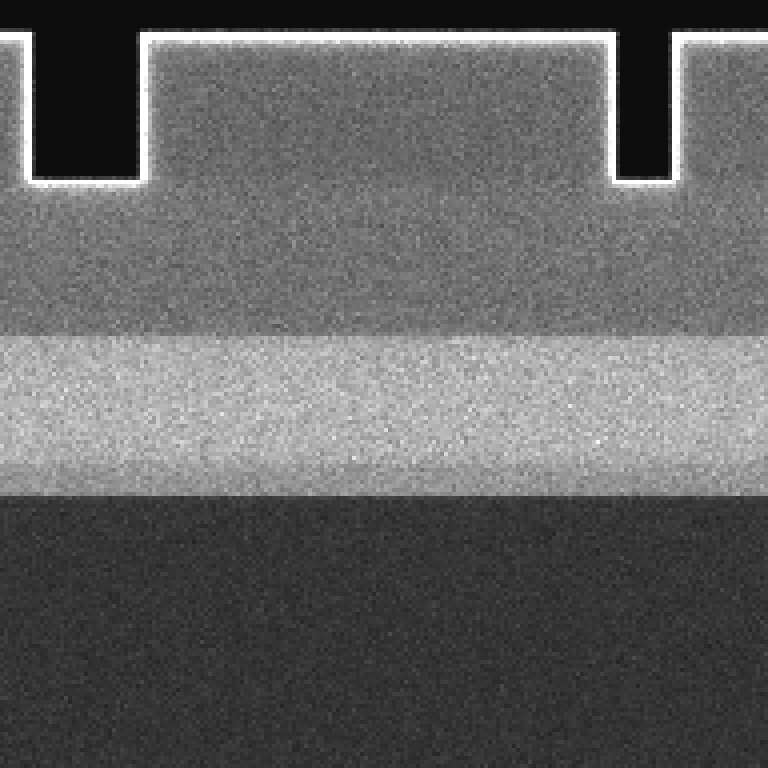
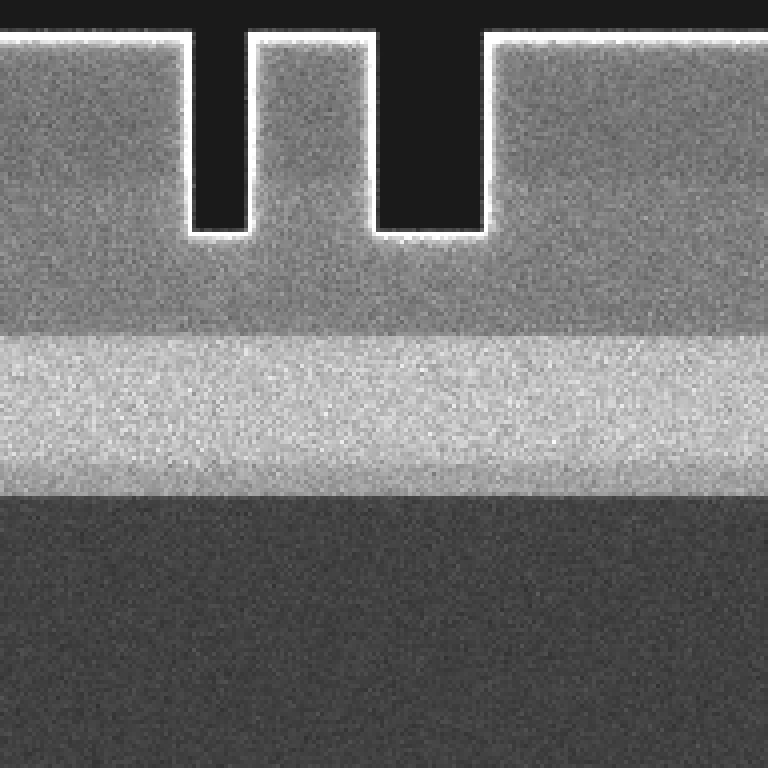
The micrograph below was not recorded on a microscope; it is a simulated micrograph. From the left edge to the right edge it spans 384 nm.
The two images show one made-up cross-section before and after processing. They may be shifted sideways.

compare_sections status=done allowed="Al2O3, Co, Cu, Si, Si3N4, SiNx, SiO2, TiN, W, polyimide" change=removed material="TiN"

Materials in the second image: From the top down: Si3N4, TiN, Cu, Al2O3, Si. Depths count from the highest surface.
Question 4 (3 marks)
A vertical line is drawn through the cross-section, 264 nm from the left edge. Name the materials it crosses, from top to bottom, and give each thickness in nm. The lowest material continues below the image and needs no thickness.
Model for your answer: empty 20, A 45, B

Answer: Si3N4 74, TiN 78, Cu 64, Al2O3 16, Si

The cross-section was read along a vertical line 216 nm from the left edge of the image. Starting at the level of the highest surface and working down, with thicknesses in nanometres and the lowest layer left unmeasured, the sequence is empty 100, TiN 52, Cu 64, Al2O3 16, Si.